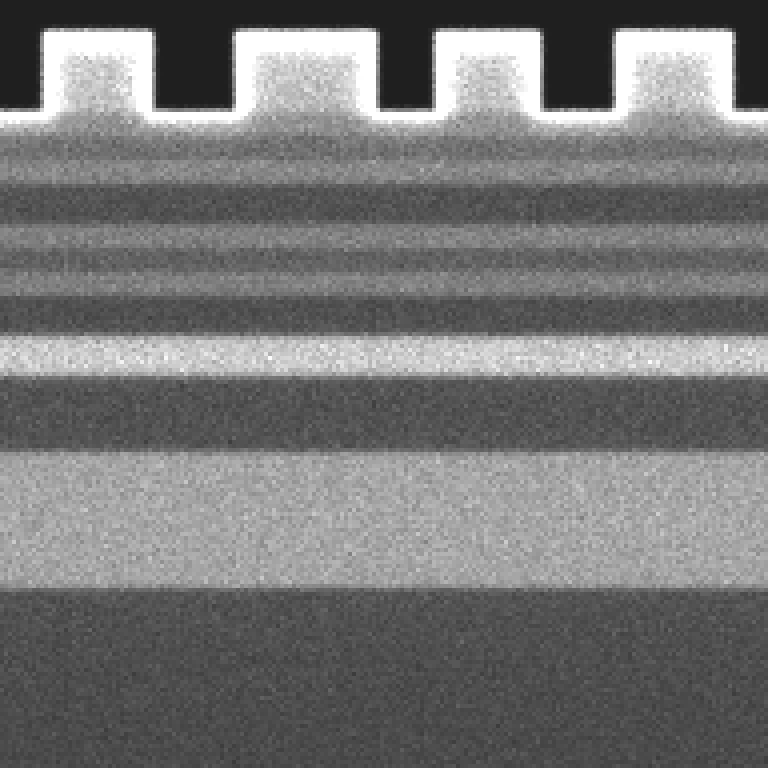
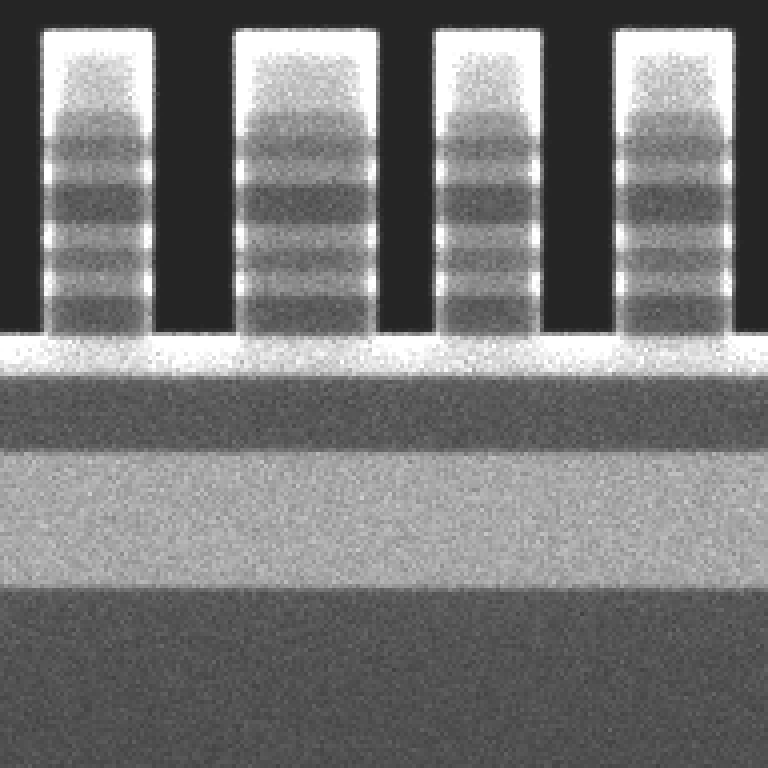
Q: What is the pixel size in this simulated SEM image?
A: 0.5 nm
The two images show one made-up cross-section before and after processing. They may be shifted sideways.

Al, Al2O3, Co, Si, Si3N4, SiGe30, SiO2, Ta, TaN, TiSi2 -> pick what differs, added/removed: Si and Si3N4 and SiGe30 removed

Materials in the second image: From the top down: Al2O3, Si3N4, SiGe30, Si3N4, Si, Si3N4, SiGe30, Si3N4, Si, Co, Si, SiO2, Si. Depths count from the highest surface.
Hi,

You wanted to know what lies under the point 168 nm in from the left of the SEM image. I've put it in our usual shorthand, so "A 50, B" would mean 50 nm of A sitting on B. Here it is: Al2O3 40, Si3N4 12, SiGe30 12, Si3N4 12, Si 20, Si3N4 12, SiGe30 12, Si3N4 12, Si 20, Co 20, Si 38, SiO2 68, Si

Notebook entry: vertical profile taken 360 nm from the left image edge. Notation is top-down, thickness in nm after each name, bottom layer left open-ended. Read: Al2O3 40, Si3N4 12, SiGe30 12, Si3N4 12, Si 20, Si3N4 12, SiGe30 12, Si3N4 12, Si 20, Co 20, Si 38, SiO2 68, Si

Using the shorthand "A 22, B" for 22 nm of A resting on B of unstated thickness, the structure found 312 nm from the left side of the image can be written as Al2O3 40, Si3N4 12, SiGe30 12, Si3N4 12, Si 20, Si3N4 12, SiGe30 12, Si3N4 12, Si 20, Co 20, Si 38, SiO2 68, Si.